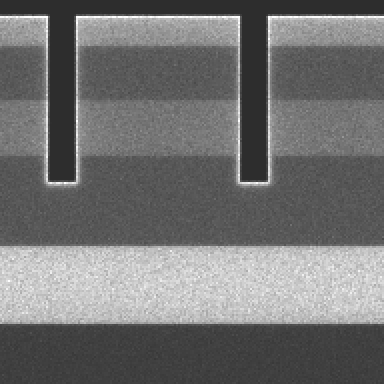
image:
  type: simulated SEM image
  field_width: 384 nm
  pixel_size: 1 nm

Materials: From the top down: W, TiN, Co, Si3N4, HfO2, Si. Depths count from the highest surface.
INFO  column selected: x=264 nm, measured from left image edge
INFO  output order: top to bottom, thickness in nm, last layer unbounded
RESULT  empty 166, Si3N4 64, HfO2 78, Si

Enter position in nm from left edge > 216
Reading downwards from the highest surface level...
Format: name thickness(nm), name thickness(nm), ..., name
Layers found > W 30, TiN 54, Co 56, Si3N4 90, HfO2 78, Si